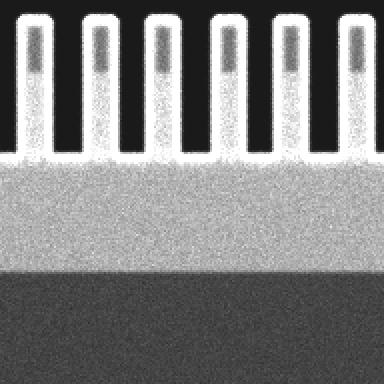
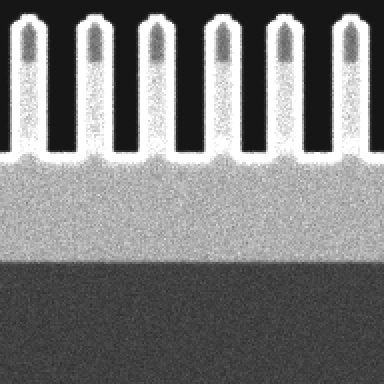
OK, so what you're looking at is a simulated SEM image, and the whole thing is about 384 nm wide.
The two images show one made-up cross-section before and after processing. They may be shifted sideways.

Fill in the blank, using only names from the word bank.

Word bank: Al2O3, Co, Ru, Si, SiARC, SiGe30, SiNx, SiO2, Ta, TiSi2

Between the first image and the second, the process removed SiO2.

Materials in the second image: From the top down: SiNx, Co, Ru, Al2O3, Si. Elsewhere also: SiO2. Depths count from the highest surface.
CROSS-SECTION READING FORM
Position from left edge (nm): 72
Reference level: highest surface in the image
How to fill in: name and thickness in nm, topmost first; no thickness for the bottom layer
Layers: empty 138, Al2O3 108, Si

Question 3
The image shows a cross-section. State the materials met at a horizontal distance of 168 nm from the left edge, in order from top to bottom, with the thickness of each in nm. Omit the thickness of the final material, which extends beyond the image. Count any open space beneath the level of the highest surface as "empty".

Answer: empty 6, SiO2 132, Al2O3 108, Si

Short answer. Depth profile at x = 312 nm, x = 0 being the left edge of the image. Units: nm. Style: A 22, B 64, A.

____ empty 138, Al2O3 108, Si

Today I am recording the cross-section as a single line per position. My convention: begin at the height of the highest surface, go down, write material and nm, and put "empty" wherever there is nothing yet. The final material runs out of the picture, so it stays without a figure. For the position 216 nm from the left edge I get SiNx 46, Co 76, Ru 16, Al2O3 108, Si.